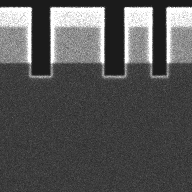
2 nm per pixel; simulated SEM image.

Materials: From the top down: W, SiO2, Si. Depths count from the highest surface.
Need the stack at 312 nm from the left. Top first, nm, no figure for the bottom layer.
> empty 136, Si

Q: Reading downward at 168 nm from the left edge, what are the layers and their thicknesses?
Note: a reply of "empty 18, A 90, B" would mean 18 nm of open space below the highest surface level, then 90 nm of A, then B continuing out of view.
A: W 38, SiO2 72, Si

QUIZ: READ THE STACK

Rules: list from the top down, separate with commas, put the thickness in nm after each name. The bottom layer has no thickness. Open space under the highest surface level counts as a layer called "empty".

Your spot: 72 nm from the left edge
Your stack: empty 136, Si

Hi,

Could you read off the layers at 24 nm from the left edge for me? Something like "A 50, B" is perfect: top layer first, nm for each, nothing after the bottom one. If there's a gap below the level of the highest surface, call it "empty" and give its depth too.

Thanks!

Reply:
W 38, SiO2 72, Si